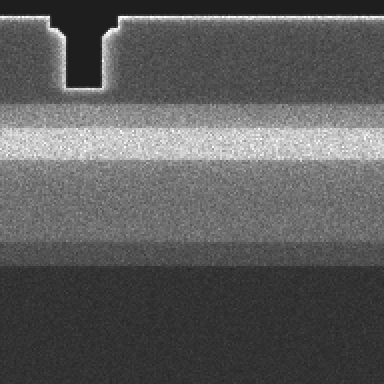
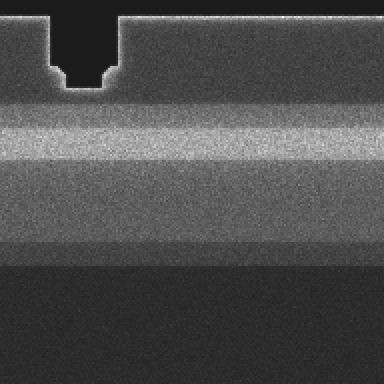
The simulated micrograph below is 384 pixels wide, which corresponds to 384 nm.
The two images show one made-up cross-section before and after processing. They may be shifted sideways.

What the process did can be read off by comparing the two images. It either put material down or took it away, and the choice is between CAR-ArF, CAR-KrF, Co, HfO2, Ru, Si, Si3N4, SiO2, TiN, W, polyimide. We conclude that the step removed SiO2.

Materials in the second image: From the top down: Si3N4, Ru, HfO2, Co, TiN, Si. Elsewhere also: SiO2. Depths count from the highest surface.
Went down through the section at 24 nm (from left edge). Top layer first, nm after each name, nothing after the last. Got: Si3N4 88, Ru 24, HfO2 32, Co 82, TiN 24, Si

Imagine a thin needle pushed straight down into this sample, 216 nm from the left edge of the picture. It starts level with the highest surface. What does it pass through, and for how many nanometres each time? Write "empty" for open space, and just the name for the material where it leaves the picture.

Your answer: Si3N4 88, Ru 24, HfO2 32, Co 82, TiN 24, Si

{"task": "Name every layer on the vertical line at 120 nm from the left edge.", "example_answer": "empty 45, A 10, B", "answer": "Si3N4 88, Ru 24, HfO2 32, Co 82, TiN 24, Si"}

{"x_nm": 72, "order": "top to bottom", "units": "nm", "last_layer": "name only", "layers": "empty 72, Si3N4 16, Ru 24, HfO2 32, Co 82, TiN 24, Si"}